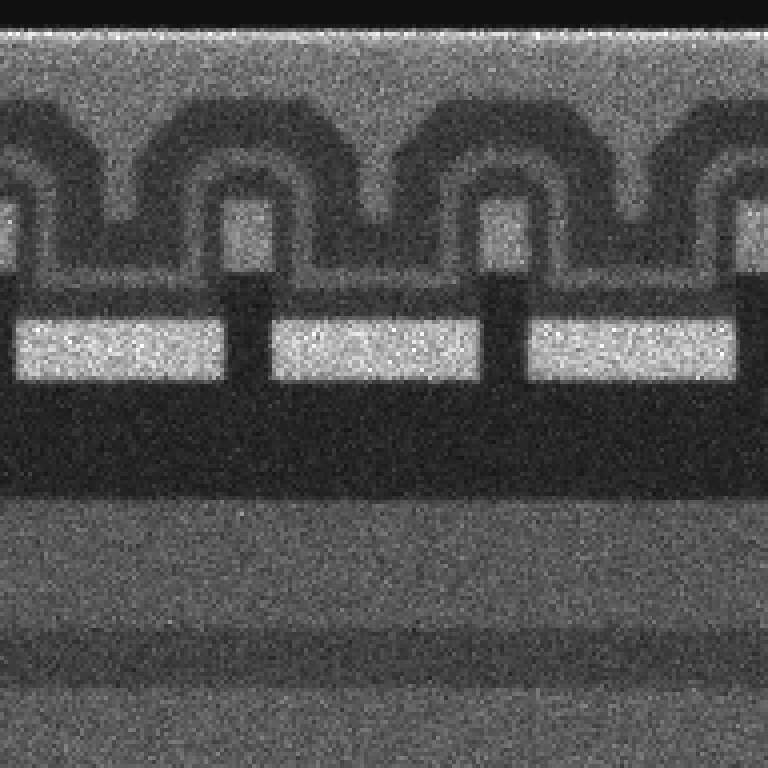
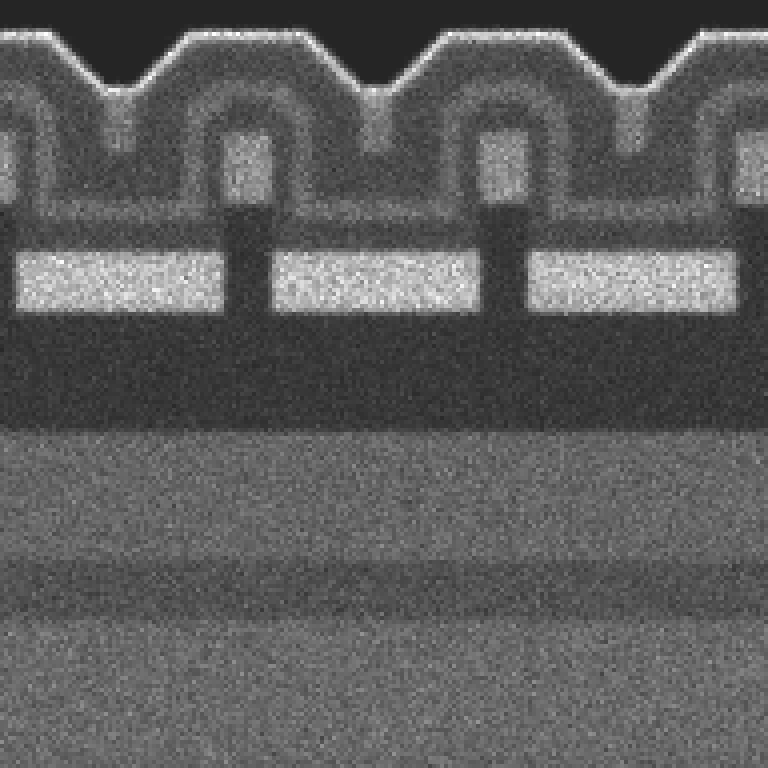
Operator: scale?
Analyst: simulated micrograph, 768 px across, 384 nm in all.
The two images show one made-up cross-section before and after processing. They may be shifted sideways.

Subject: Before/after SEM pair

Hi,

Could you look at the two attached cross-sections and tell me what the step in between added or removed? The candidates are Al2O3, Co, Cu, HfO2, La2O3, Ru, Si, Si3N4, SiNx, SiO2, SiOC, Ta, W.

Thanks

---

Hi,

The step removed Ru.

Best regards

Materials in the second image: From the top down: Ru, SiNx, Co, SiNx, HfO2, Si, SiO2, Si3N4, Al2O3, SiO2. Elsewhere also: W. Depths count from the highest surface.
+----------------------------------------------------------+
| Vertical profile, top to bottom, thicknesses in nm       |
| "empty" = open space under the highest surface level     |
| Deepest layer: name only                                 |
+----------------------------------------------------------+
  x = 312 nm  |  empty 28, Ru 32, SiNx 24, Co 10, SiNx 16, HfO2 30, Si 60, SiO2 64, Si3N4 30, Al2O3 68, SiO2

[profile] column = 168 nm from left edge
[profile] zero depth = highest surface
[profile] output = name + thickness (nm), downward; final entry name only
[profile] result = empty 16, SiNx 68, Co 10, SiNx 16, HfO2 30, Si 60, SiO2 64, Si3N4 30, Al2O3 68, SiO2